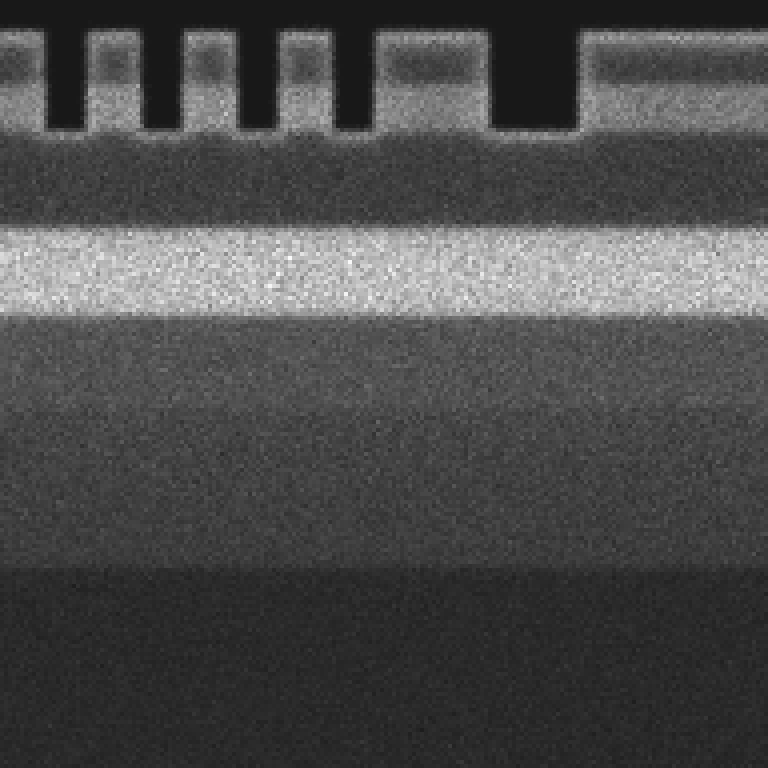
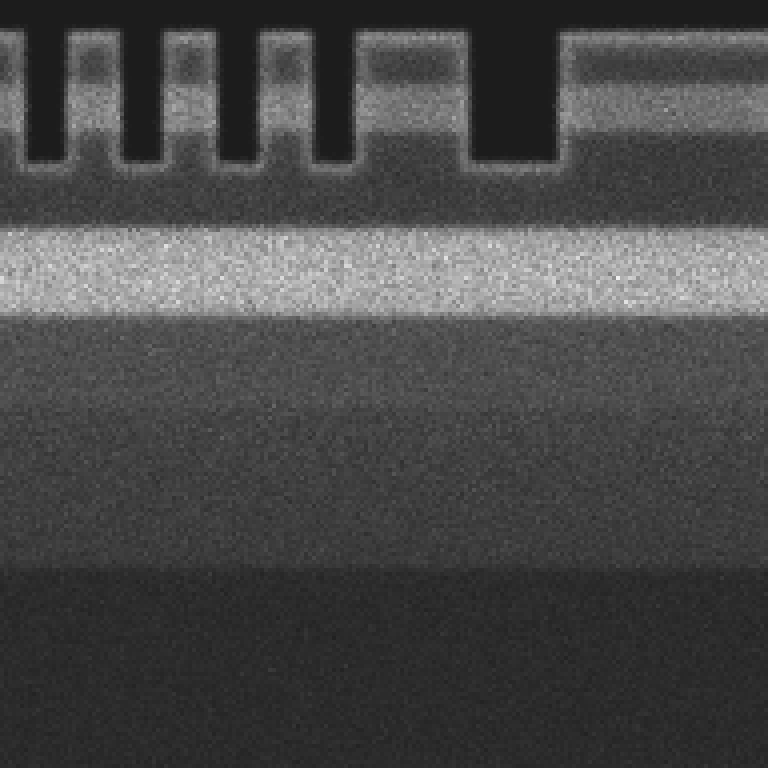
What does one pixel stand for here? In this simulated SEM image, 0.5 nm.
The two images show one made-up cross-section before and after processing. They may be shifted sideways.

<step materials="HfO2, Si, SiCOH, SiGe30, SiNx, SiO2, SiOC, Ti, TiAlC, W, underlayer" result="removed SiNx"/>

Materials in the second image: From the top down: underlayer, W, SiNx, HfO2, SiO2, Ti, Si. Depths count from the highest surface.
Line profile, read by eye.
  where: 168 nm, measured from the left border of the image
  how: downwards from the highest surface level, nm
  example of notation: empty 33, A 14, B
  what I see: empty 66, SiNx 32, HfO2 44, SiO2 46, Ti 80, Si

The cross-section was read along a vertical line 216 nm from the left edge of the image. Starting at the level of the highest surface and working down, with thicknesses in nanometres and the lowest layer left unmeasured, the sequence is underlayer 26, W 24, SiNx 48, HfO2 44, SiO2 46, Ti 80, Si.